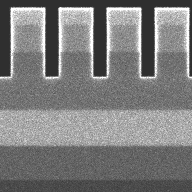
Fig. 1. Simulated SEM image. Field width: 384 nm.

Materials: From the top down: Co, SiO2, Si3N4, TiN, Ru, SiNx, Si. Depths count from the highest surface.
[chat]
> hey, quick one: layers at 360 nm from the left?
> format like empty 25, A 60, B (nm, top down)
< Co 34, SiO2 54, Si3N4 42, TiN 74, Ru 72, SiNx 68, Si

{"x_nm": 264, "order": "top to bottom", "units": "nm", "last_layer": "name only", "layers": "Co 34, SiO2 54, Si3N4 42, TiN 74, Ru 72, SiNx 68, Si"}